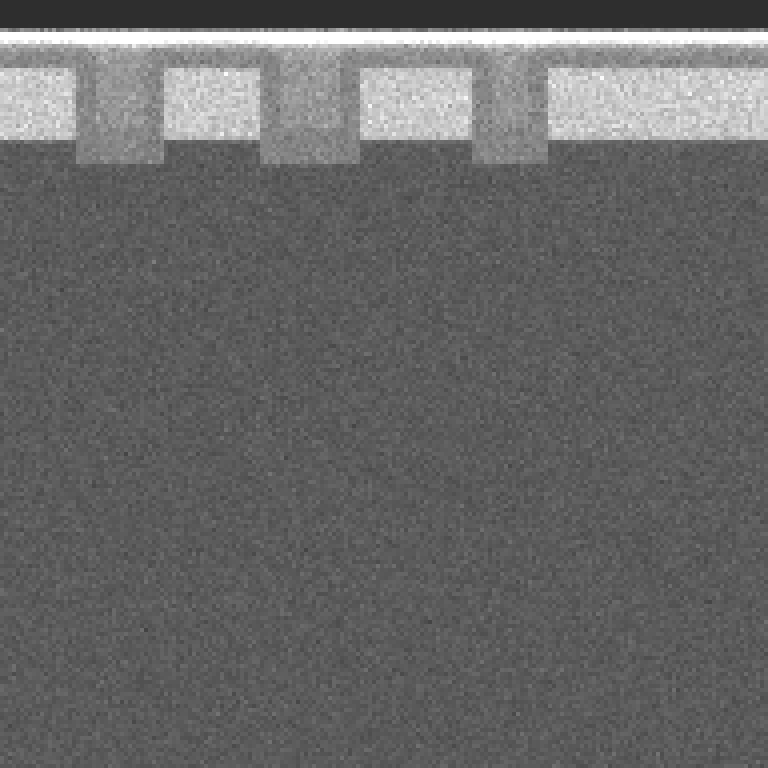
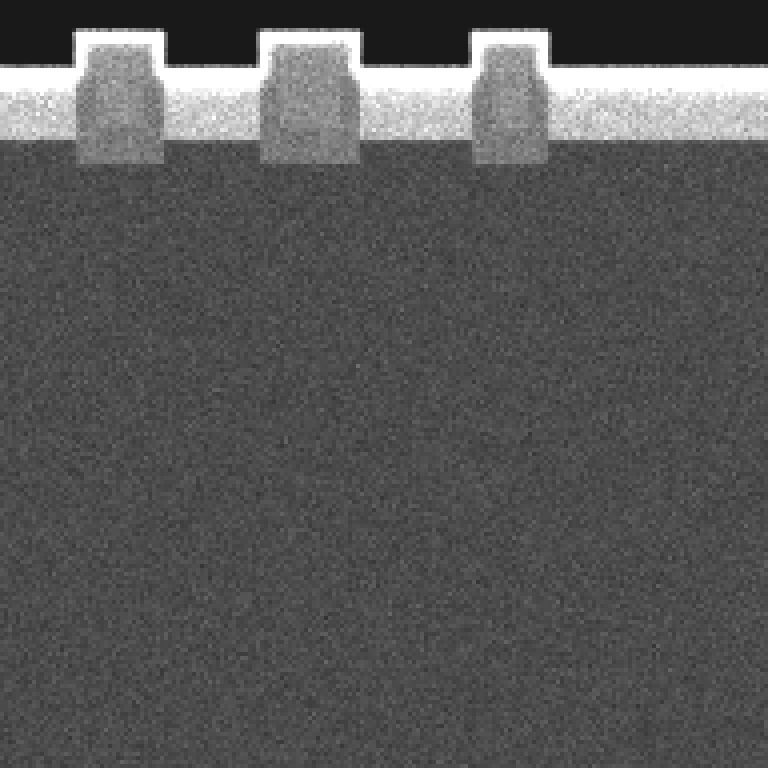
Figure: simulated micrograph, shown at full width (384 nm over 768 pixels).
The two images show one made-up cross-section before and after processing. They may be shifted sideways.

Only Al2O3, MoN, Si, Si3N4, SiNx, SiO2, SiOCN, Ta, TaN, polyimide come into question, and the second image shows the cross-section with SiOCN removed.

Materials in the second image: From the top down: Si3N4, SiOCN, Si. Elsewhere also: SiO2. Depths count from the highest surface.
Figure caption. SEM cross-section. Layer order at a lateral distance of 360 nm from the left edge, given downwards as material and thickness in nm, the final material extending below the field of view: empty 18, SiO2 36, Si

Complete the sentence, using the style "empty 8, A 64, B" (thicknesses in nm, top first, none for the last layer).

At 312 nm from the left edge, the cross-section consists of empty 18, SiO2 36, Si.